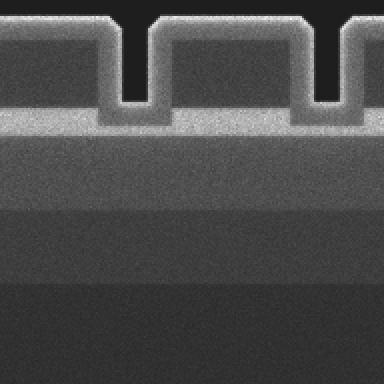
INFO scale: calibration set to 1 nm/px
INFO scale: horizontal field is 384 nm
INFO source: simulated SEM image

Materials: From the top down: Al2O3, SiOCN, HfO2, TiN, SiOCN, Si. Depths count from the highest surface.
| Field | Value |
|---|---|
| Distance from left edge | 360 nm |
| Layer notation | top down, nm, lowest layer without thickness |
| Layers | Al2O3 110, HfO2 10, TiN 74, SiOCN 74, Si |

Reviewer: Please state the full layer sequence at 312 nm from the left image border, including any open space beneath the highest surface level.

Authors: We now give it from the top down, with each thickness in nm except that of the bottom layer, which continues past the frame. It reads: empty 12, Al2O3 98, HfO2 10, TiN 74, SiOCN 74, Si